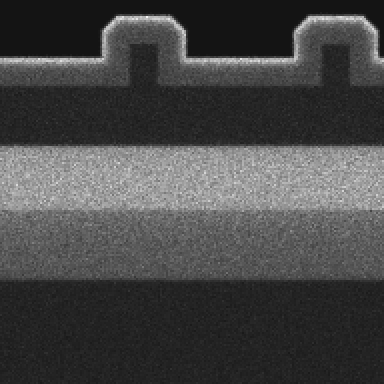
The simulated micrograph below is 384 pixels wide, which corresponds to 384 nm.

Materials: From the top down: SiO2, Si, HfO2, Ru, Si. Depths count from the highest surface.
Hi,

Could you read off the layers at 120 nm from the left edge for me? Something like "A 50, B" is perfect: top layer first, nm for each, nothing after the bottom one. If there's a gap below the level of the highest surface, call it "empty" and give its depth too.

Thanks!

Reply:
SiO2 70, Si 60, HfO2 64, Ru 70, Si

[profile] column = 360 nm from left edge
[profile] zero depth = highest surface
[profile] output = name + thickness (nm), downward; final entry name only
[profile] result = SiO2 70, Si 60, HfO2 64, Ru 70, Si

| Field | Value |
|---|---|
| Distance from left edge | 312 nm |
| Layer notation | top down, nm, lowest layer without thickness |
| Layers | SiO2 70, Si 60, HfO2 64, Ru 70, Si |